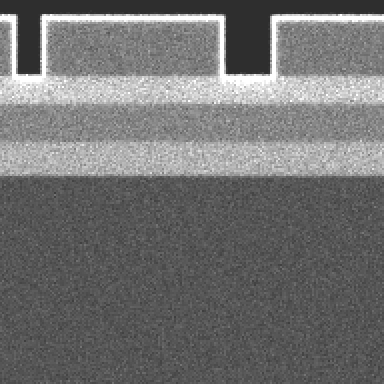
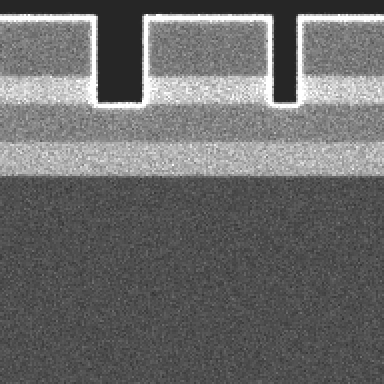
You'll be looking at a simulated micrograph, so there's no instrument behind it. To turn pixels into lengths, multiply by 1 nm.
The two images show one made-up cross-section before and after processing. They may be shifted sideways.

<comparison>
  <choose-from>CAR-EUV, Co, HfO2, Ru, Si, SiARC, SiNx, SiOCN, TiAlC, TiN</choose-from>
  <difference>Ru removed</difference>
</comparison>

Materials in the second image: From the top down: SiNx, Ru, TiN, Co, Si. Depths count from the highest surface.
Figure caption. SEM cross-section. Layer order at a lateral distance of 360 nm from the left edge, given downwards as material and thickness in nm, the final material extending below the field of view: SiNx 60, Ru 28, TiN 38, Co 34, Si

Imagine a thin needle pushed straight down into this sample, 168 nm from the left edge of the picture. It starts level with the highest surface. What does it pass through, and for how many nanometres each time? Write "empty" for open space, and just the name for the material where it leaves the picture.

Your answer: SiNx 60, Ru 28, TiN 38, Co 34, Si